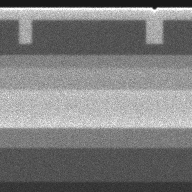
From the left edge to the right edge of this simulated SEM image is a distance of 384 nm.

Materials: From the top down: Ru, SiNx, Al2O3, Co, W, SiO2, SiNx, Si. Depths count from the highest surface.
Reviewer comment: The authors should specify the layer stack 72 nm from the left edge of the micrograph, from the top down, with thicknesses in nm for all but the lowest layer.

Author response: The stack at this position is Ru 24, SiNx 70, Al2O3 26, Co 44, W 76, SiO2 40, SiNx 68, Si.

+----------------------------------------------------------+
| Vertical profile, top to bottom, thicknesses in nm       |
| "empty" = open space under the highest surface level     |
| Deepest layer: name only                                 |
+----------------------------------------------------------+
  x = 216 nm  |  Ru 24, SiNx 70, Al2O3 26, Co 44, W 76, SiO2 40, SiNx 68, Si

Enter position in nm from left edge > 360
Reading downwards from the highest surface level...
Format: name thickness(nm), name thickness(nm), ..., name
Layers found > Ru 24, SiNx 70, Al2O3 26, Co 44, W 76, SiO2 40, SiNx 68, Si